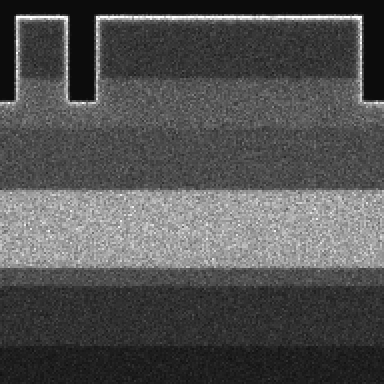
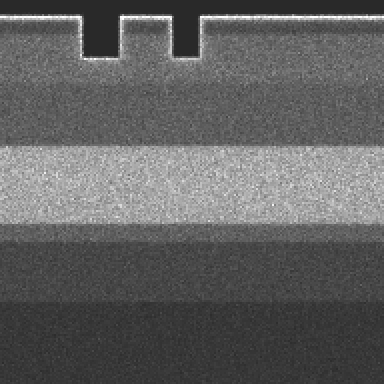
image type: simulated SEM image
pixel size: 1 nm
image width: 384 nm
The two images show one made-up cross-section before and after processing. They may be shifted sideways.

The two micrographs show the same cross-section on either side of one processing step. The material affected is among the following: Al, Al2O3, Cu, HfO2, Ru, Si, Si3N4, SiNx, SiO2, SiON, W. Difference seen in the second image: Si3N4 removed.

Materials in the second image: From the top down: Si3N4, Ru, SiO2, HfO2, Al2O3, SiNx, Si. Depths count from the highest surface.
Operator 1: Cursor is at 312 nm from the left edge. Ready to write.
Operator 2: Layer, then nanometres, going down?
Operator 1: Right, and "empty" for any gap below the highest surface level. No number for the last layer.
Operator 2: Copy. Si3N4 18, Ru 50, SiO2 62, HfO2 78, Al2O3 18, SiNx 60, Si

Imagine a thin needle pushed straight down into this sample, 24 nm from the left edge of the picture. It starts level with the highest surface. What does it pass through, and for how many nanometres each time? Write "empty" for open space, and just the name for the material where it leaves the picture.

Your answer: Si3N4 18, Ru 50, SiO2 62, HfO2 78, Al2O3 18, SiNx 60, Si